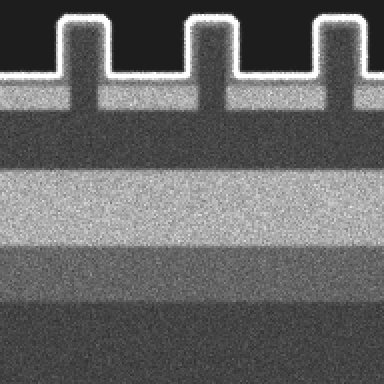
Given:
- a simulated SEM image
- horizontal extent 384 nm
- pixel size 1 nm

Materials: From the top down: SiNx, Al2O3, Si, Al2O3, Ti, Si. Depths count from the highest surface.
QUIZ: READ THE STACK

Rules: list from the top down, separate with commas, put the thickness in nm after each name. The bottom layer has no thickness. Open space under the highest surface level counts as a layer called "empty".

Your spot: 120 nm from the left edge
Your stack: empty 58, SiNx 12, Al2O3 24, Si 60, Al2O3 76, Ti 56, Si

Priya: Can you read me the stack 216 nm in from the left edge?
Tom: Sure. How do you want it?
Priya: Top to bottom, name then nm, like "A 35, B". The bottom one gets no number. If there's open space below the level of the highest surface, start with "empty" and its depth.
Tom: SiNx 12, Si 142, Al2O3 76, Ti 56, Si